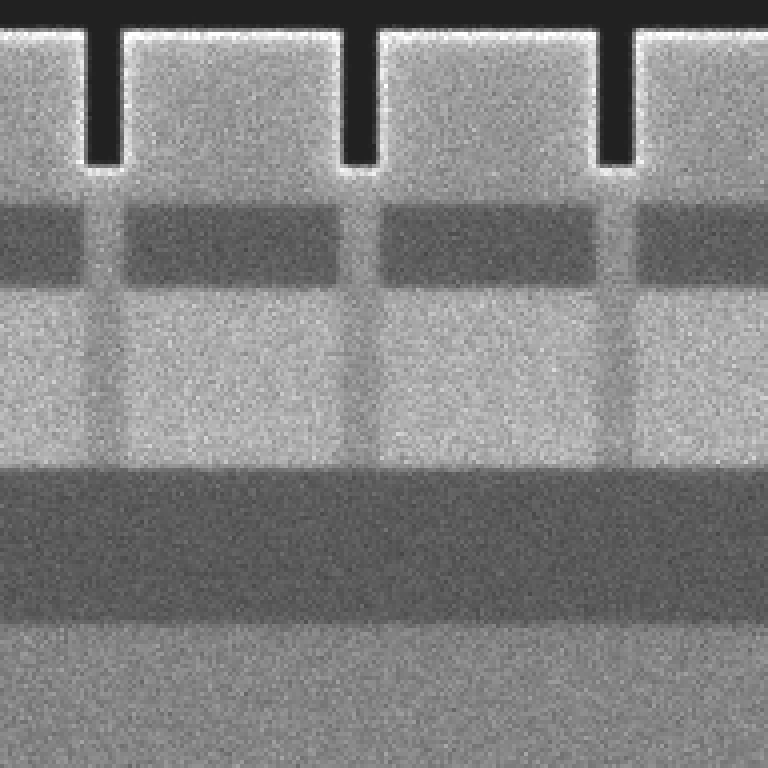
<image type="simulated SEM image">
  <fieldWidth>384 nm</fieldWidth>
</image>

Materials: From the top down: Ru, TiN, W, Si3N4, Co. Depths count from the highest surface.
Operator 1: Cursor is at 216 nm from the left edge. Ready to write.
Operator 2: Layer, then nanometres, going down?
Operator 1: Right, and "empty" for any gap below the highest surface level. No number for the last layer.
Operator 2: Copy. Ru 86, TiN 42, W 90, Si3N4 78, Co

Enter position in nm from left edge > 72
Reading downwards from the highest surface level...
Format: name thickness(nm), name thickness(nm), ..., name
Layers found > Ru 86, TiN 42, W 90, Si3N4 78, Co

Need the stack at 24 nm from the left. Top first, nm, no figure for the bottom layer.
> Ru 86, TiN 42, W 90, Si3N4 78, Co